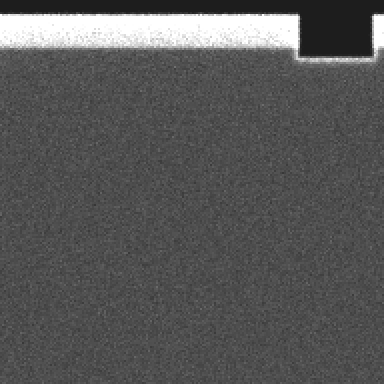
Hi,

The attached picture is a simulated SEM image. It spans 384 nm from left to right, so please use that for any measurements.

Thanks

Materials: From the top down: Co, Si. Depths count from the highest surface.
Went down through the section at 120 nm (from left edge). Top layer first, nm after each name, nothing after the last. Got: Co 32, Si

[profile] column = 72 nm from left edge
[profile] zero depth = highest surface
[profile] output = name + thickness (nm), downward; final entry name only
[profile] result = Co 32, Si